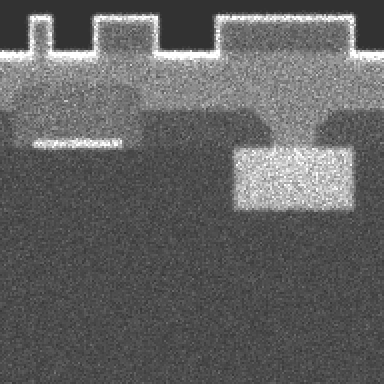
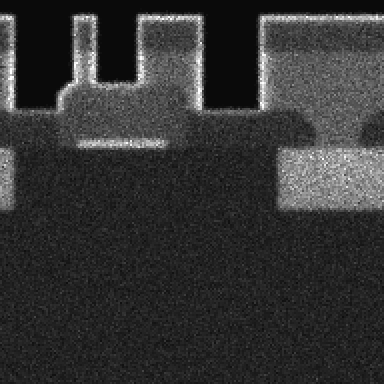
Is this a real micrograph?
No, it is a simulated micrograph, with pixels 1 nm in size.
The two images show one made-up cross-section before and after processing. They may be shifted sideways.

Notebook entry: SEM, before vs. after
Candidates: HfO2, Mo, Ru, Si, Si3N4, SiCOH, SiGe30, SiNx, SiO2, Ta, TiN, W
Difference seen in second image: SiO2 removed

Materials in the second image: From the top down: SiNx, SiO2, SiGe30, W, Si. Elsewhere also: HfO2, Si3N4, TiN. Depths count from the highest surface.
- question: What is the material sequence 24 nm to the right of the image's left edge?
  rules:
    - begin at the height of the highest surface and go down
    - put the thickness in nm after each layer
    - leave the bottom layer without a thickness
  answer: empty 94, SiGe30 38, Si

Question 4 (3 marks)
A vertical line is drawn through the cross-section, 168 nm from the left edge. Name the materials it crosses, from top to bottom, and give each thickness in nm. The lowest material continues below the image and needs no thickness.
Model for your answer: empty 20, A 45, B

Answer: SiNx 36, SiO2 32, Si3N4 64, Si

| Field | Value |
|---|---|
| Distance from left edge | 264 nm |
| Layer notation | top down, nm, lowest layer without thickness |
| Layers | SiNx 36, SiO2 58, SiGe30 38, Si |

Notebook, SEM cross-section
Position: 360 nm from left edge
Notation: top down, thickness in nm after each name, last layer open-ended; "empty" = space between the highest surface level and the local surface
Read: SiNx 36, SiO2 76, SiGe30 20, W 62, Si